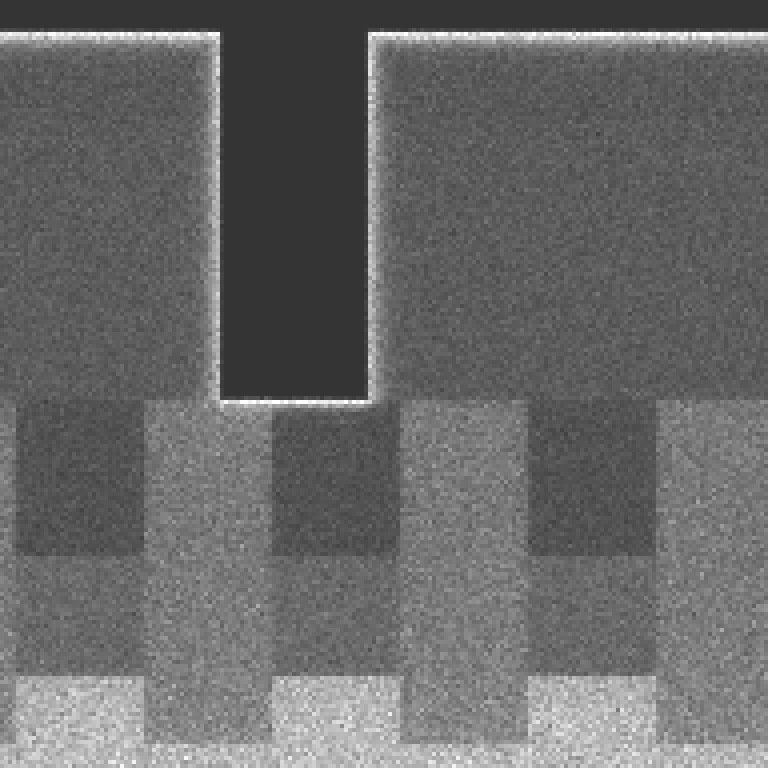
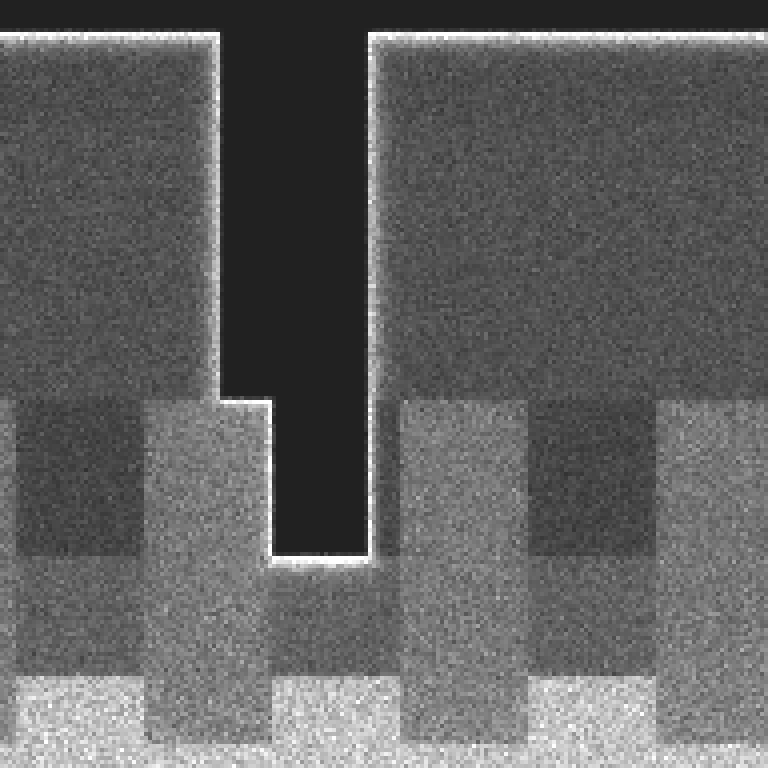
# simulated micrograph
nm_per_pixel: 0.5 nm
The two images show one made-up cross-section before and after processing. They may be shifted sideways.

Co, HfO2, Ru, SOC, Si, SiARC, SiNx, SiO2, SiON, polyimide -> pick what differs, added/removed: SiNx removed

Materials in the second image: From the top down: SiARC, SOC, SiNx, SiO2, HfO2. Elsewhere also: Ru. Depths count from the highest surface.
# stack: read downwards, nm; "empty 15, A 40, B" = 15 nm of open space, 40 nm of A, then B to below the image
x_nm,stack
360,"SiARC 44, SOC 140, Ru 172, HfO2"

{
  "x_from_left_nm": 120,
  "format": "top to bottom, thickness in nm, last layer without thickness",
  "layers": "empty 184, Ru 172, HfO2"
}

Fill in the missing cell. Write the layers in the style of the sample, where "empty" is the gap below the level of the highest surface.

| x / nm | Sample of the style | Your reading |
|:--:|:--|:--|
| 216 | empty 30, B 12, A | SiARC 44, SOC 140, Ru 172, HfO2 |